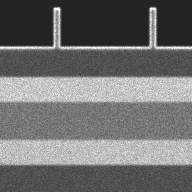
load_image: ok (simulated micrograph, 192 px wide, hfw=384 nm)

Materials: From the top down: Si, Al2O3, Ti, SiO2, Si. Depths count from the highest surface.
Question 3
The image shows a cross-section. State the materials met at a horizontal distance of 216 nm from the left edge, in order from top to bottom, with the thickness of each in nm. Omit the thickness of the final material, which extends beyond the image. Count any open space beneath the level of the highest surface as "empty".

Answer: empty 78, Si 60, Al2O3 50, Ti 76, SiO2 50, Si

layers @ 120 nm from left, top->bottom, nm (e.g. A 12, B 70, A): empty 78, Si 60, Al2O3 50, Ti 76, SiO2 50, Si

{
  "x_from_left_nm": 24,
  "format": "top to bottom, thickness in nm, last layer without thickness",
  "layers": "empty 78, Si 60, Al2O3 50, Ti 76, SiO2 50, Si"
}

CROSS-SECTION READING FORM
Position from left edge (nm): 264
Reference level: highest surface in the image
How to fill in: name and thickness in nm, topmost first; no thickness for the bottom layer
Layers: empty 78, Si 60, Al2O3 50, Ti 76, SiO2 50, Si